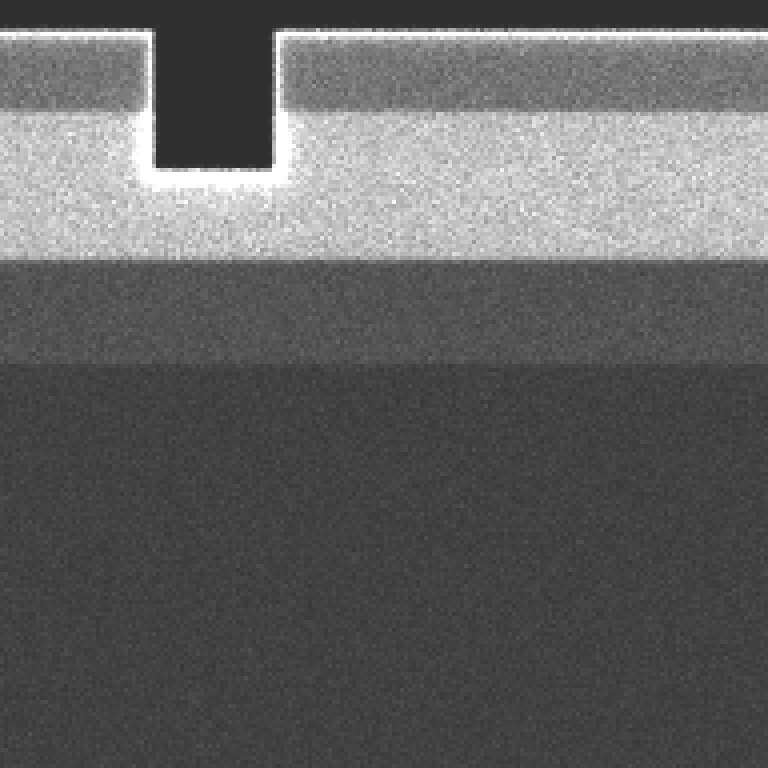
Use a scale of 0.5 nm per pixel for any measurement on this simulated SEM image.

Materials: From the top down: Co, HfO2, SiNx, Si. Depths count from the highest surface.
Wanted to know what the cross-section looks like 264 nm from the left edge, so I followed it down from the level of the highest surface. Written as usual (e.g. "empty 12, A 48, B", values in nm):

Co 40, HfO2 74, SiNx 52, Si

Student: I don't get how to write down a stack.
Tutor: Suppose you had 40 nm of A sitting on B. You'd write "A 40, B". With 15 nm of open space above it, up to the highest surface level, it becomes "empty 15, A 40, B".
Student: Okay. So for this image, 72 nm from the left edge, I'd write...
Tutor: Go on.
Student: Co 40, HfO2 74, SiNx 52, Si